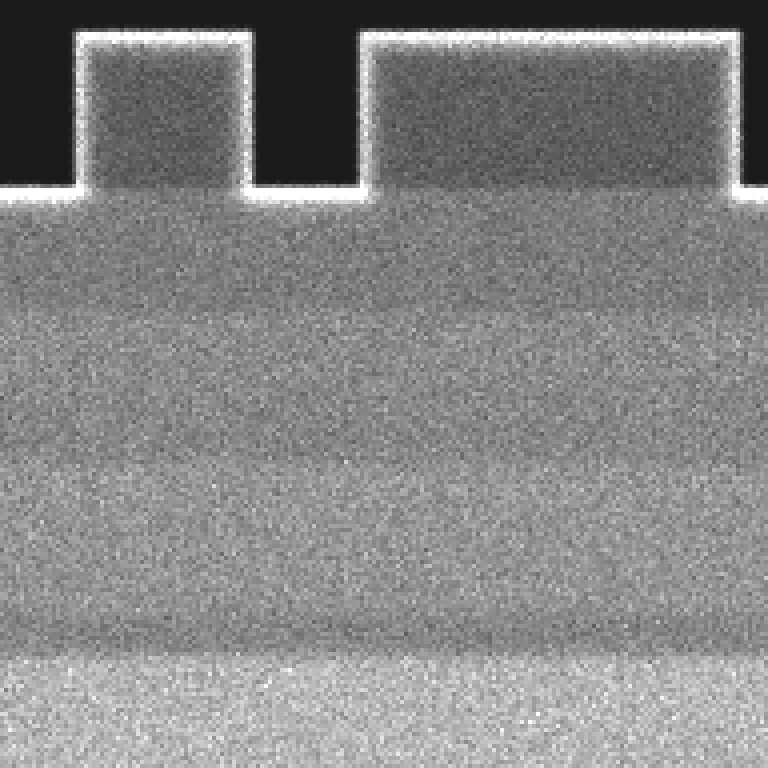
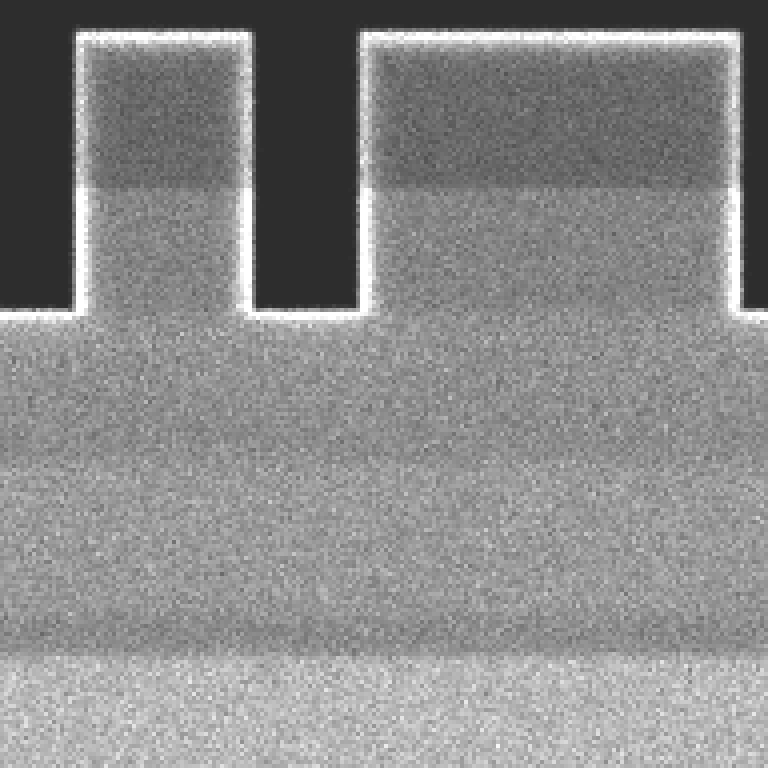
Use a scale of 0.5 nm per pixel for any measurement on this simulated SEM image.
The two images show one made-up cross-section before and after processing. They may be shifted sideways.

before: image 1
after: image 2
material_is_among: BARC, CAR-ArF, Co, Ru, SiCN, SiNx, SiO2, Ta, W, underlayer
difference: SiO2, removed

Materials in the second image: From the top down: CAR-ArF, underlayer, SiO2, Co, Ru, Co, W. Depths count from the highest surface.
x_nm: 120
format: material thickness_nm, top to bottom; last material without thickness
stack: CAR-ArF 50, underlayer 28, SiO2 62, Co 76, Ru 76, Co 20, W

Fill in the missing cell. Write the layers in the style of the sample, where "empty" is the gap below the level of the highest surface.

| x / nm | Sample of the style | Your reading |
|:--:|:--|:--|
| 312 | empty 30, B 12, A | CAR-ArF 50, underlayer 28, SiO2 62, Co 76, Ru 76, Co 20, W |